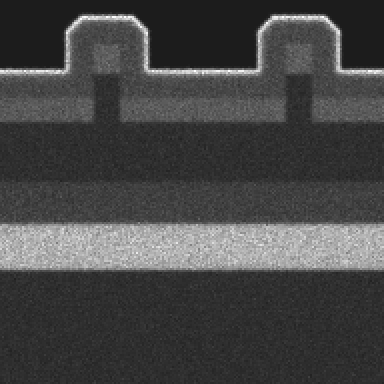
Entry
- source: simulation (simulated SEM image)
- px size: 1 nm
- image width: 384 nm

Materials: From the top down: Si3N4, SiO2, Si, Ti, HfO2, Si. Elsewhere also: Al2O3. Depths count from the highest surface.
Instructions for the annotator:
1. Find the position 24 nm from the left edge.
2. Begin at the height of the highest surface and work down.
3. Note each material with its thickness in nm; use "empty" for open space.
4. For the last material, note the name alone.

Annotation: empty 54, Si3N4 28, SiO2 24, Si 60, Ti 42, HfO2 46, Si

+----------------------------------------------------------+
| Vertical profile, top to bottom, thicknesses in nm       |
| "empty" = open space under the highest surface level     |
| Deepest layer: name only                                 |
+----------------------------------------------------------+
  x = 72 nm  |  empty 8, Si3N4 74, SiO2 24, Si 60, Ti 42, HfO2 46, Si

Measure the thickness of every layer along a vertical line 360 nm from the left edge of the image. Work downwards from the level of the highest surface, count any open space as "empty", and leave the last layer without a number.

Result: empty 54, Si3N4 28, SiO2 24, Si 60, Ti 42, HfO2 46, Si